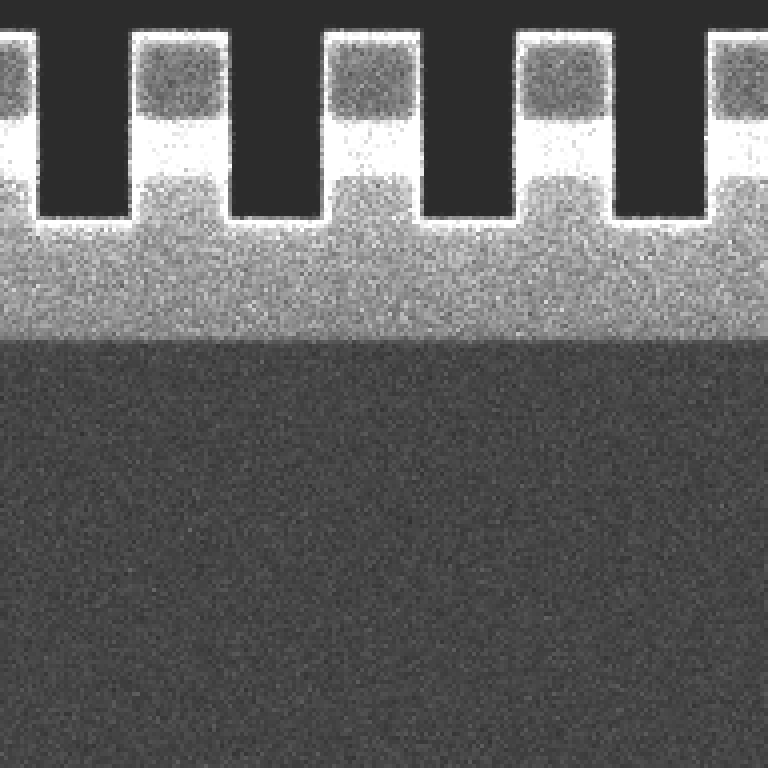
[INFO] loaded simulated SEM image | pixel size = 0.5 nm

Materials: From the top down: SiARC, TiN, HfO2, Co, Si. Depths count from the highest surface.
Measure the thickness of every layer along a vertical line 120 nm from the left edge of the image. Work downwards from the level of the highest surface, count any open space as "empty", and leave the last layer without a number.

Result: empty 94, Co 60, Si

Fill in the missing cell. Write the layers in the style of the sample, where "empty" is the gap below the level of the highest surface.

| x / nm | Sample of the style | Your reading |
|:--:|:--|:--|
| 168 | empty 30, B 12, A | SiARC 12, TiN 32, HfO2 28, Co 82, Si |